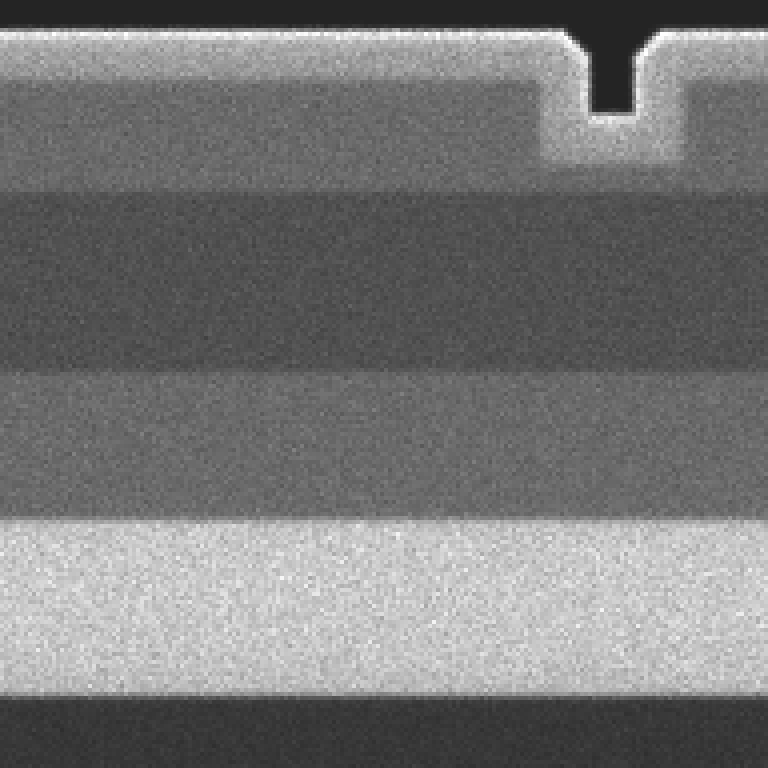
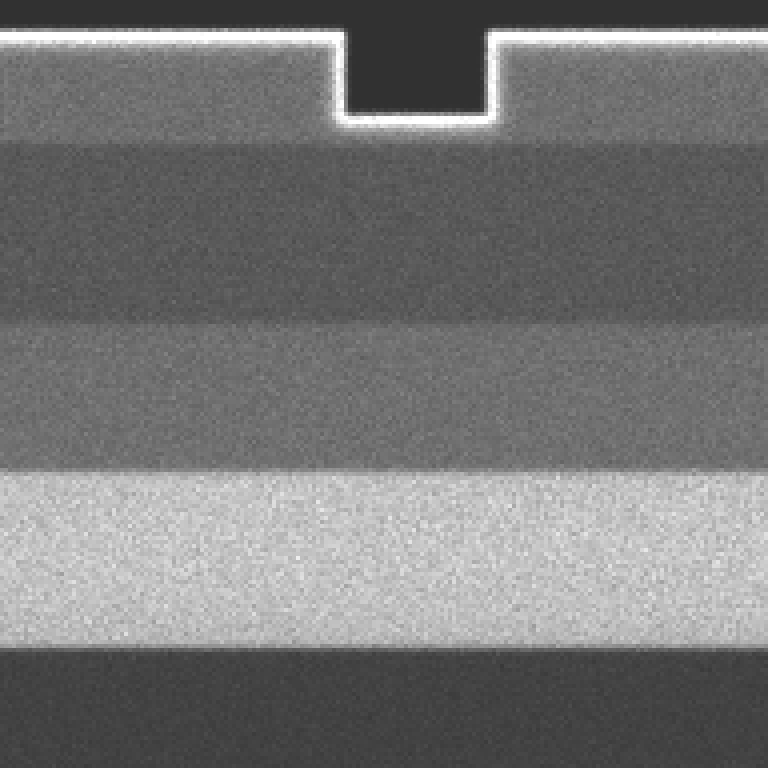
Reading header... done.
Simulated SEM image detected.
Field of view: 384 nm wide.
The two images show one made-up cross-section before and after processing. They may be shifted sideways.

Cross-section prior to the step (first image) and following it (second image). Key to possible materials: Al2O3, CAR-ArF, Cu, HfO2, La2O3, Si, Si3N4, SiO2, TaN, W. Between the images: W was removed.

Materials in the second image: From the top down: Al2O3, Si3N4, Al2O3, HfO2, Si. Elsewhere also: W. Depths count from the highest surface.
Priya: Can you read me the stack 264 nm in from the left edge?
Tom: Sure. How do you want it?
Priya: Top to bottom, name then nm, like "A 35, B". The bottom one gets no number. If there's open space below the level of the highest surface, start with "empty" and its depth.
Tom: Al2O3 56, Si3N4 90, Al2O3 74, HfO2 88, Si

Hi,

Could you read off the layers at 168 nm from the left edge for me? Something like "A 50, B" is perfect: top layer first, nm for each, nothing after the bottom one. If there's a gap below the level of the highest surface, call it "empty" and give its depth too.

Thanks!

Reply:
Al2O3 56, Si3N4 90, Al2O3 74, HfO2 88, Si